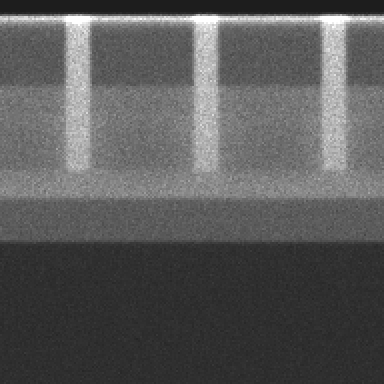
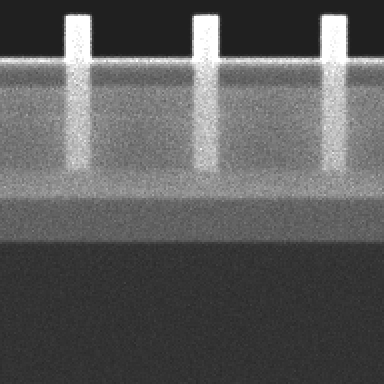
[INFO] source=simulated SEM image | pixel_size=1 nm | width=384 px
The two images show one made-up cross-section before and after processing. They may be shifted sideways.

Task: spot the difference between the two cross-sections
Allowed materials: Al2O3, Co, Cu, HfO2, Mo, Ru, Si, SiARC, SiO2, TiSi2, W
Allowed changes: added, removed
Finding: removed SiO2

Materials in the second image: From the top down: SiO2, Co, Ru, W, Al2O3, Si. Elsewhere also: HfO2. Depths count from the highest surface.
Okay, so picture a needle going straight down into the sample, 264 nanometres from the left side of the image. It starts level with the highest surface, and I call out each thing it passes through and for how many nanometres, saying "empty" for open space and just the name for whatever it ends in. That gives empty 42, SiO2 28, Co 28, Ru 56, W 28, Al2O3 44, Si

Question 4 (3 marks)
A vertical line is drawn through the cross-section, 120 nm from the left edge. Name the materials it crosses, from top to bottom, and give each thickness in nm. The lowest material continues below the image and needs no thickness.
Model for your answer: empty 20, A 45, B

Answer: empty 42, SiO2 28, Co 28, Ru 56, W 28, Al2O3 44, Si